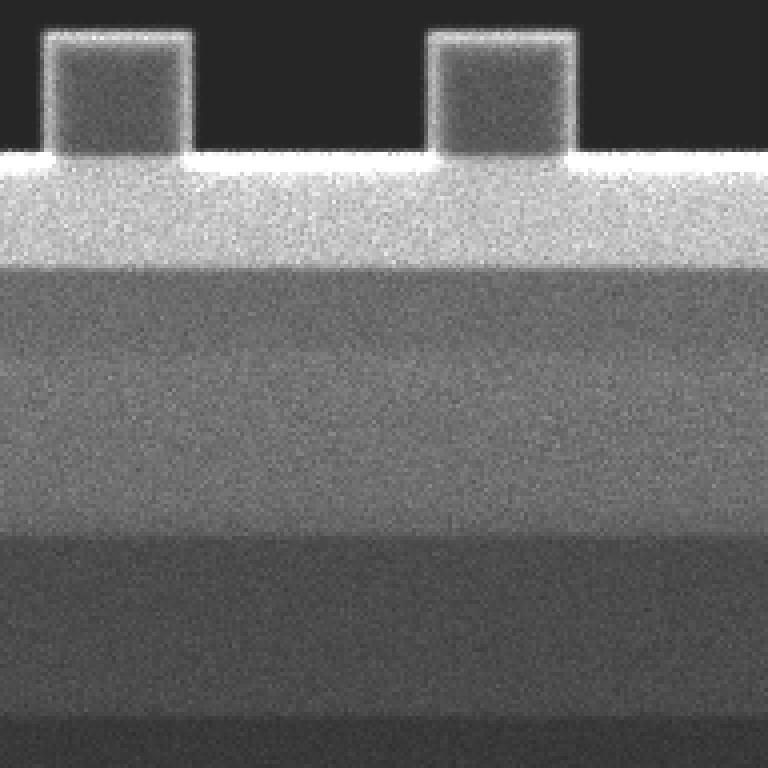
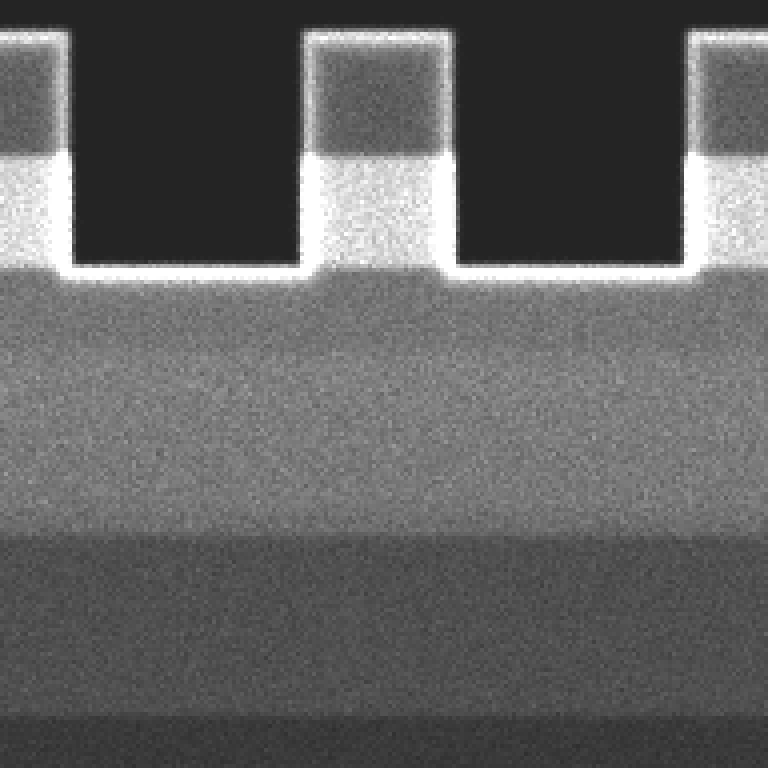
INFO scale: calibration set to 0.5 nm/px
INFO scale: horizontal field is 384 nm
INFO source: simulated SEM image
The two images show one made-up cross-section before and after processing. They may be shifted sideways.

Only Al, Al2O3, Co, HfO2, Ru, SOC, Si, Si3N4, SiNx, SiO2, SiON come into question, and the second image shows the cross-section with HfO2 removed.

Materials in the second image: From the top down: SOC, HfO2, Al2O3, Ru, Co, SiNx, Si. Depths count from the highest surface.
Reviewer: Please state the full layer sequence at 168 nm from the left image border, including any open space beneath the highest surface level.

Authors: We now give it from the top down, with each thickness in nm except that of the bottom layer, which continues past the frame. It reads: SOC 62, HfO2 56, Al2O3 42, Ru 80, Co 12, SiNx 90, Si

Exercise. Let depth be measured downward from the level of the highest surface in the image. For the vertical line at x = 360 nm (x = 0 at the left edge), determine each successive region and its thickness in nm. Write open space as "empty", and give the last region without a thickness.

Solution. SOC 62, HfO2 56, Al2O3 42, Ru 80, Co 12, SiNx 90, Si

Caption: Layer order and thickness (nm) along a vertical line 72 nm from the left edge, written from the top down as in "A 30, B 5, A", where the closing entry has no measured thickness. empty 118, Al2O3 42, Ru 80, Co 12, SiNx 90, Si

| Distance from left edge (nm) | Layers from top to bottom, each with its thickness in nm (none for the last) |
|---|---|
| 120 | empty 118, Al2O3 42, Ru 80, Co 12, SiNx 90, Si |